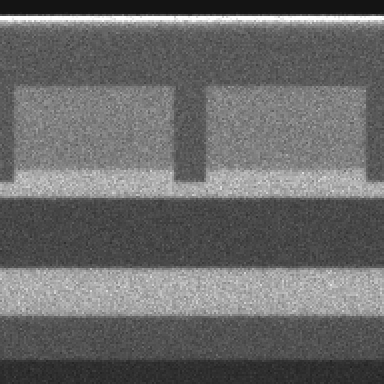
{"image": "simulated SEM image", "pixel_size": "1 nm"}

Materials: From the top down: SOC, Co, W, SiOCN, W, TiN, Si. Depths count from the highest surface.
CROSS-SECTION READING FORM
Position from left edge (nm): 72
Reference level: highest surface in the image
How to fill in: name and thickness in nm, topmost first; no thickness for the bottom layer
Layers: SOC 70, Co 84, W 28, SiOCN 70, W 48, TiN 44, Si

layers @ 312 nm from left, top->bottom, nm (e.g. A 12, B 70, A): SOC 70, Co 84, W 28, SiOCN 70, W 48, TiN 44, Si